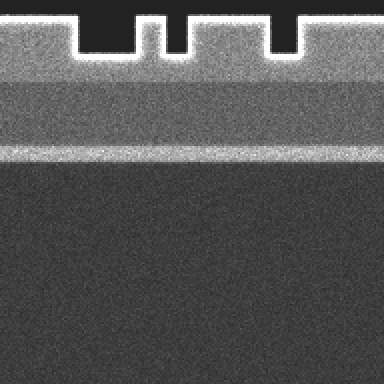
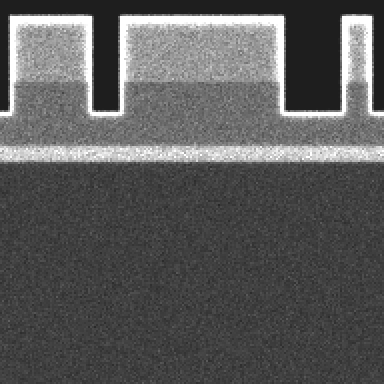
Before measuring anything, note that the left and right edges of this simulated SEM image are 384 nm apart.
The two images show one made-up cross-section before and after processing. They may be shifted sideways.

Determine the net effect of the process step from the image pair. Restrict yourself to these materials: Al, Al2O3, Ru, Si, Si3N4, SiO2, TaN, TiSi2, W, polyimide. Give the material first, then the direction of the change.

Al2O3 and Si3N4: removed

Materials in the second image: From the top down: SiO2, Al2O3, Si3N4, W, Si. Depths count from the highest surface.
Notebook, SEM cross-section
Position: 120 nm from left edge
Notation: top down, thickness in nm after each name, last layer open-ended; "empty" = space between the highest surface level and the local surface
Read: SiO2 20, Al2O3 46, Si3N4 64, W 16, Si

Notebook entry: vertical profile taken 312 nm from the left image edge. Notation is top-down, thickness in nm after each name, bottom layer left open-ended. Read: empty 96, Si3N4 34, W 16, Si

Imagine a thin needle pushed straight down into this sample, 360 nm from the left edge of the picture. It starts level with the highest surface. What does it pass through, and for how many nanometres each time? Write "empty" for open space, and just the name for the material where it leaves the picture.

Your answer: SiO2 20, Al2O3 46, Si3N4 64, W 16, Si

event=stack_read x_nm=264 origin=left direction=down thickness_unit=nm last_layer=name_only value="SiO2 20, Al2O3 46, Si3N4 64, W 16, Si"